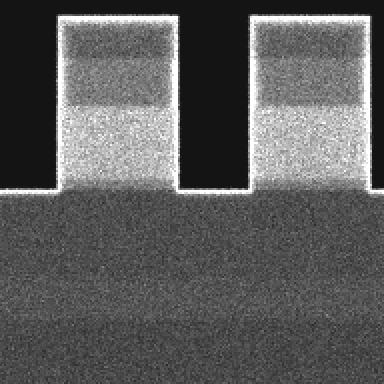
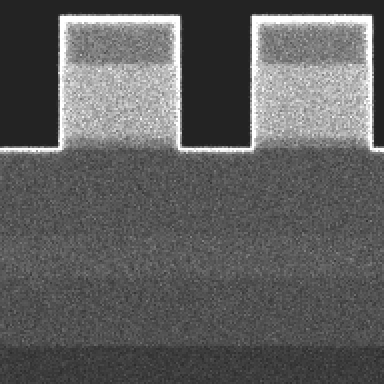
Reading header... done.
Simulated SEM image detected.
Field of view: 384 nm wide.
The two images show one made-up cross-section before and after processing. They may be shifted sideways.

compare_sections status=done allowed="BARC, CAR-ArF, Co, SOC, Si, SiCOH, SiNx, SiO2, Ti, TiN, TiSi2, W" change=removed material="SOC"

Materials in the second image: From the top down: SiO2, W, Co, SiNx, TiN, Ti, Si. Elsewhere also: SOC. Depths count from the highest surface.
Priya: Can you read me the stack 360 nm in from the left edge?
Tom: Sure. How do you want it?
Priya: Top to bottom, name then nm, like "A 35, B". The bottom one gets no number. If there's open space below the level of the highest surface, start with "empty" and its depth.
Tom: SiO2 48, W 74, Co 10, SiNx 88, TiN 42, Ti 68, Si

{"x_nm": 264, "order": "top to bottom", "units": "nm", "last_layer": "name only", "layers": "SiO2 48, W 74, Co 10, SiNx 88, TiN 42, Ti 68, Si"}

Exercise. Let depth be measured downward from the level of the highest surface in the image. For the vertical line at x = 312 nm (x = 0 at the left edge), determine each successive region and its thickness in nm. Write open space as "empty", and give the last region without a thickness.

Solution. SiO2 48, W 74, Co 10, SiNx 88, TiN 42, Ti 68, Si